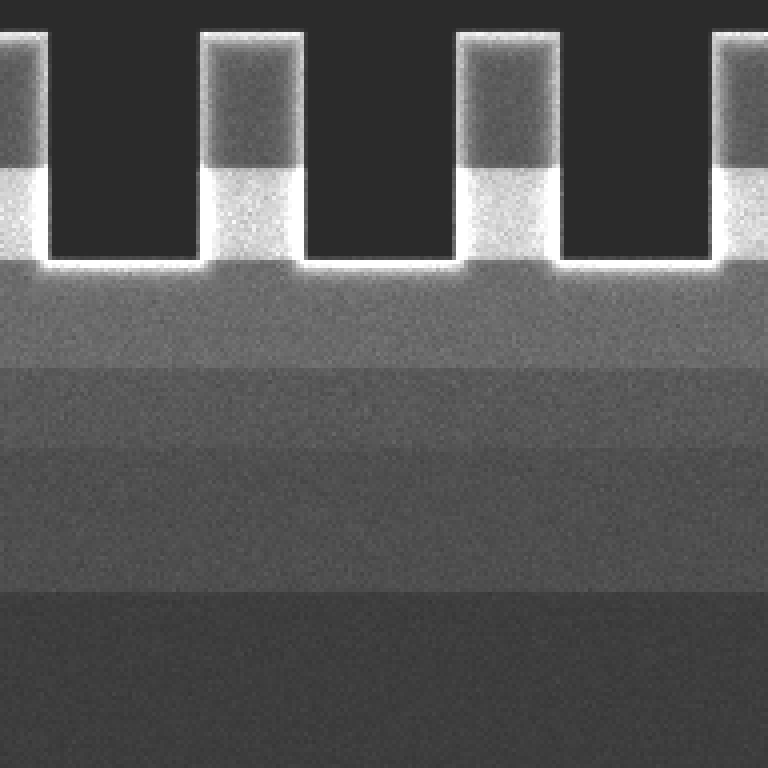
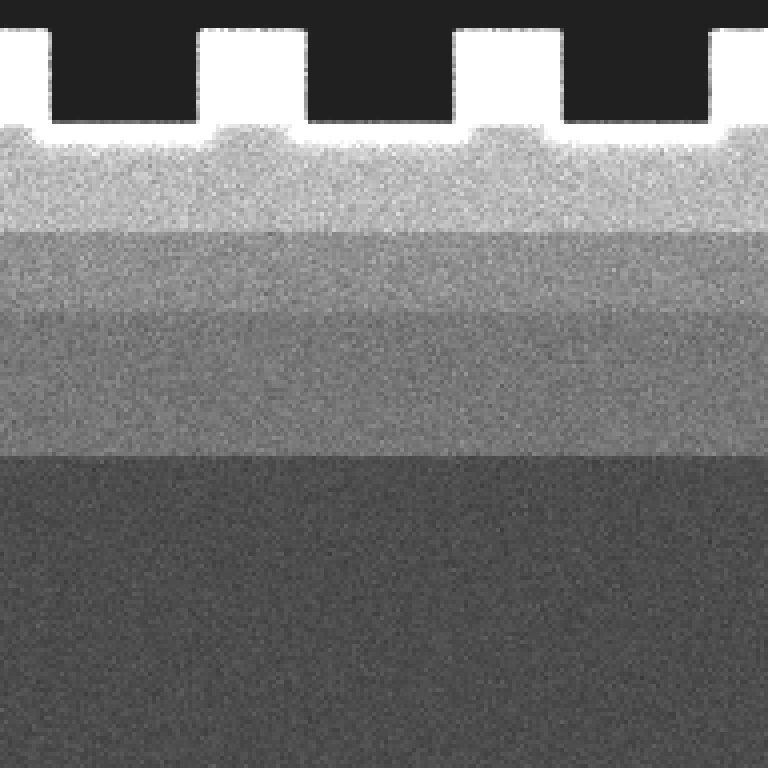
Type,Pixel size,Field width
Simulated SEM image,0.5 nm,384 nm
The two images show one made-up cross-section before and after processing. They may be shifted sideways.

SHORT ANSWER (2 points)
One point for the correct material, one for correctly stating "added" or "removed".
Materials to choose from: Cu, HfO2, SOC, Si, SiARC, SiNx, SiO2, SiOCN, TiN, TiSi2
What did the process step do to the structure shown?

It removed SOC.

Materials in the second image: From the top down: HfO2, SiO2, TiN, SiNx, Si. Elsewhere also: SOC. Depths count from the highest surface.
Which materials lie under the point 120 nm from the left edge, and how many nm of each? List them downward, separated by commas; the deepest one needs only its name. HfO2 46, SiO2 54, TiN 40, SiNx 72, Si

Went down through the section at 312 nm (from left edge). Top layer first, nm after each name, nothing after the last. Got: empty 46, SiO2 54, TiN 40, SiNx 72, Si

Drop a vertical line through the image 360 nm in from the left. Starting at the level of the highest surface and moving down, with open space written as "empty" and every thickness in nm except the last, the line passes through HfO2 46, SiO2 54, TiN 40, SiNx 72, Si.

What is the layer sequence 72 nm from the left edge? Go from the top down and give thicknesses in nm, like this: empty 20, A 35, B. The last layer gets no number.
empty 46, SiO2 54, TiN 40, SiNx 72, Si